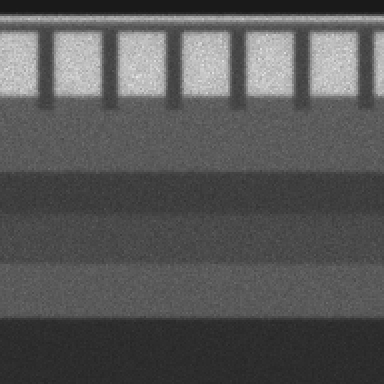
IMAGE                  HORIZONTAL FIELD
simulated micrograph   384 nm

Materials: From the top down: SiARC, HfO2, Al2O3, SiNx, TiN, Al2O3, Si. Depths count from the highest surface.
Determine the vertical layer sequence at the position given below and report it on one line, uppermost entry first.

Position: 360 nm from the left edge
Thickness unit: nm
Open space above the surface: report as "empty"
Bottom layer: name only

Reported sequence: SiARC 94, Al2O3 62, SiNx 42, TiN 50, Al2O3 54, Si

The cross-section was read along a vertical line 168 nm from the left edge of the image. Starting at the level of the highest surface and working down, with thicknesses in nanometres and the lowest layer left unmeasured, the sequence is SiARC 94, Al2O3 62, SiNx 42, TiN 50, Al2O3 54, Si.